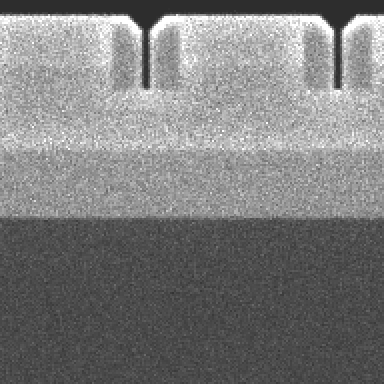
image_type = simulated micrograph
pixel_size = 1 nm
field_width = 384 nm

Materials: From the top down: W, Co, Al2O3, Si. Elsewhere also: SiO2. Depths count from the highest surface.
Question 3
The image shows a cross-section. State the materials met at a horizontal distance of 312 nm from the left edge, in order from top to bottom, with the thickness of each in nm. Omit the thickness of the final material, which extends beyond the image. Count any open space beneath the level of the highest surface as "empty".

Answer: SiO2 74, Co 60, Al2O3 68, Si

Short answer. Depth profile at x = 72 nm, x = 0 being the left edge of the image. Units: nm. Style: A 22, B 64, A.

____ W 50, Co 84, Al2O3 68, Si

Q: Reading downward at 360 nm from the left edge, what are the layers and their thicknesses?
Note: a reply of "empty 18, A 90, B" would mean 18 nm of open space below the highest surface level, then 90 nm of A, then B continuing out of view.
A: SiO2 74, Co 60, Al2O3 68, Si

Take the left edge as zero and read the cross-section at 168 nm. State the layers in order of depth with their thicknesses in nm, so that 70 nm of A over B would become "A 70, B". SiO2 74, Co 60, Al2O3 68, Si